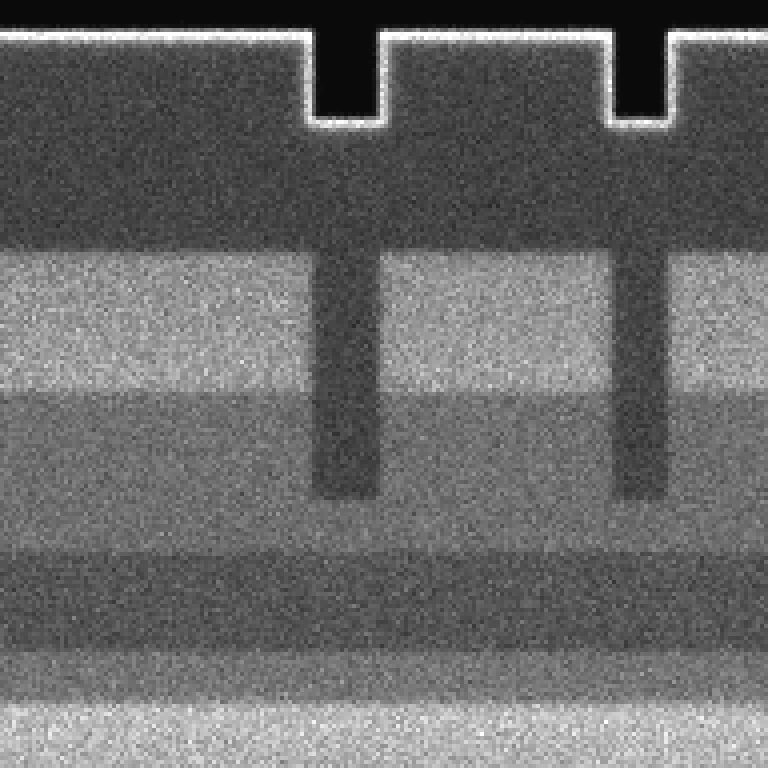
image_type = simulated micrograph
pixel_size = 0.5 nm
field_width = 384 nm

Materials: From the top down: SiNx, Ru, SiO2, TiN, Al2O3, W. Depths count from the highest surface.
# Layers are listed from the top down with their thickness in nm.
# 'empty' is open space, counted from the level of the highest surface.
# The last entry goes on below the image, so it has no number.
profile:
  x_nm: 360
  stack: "SiNx 110, Ru 70, SiO2 80, TiN 50, Al2O3 26, W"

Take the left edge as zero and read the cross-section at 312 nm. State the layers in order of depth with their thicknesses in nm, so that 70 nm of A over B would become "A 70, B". empty 44, SiNx 190, SiO2 26, TiN 50, Al2O3 26, W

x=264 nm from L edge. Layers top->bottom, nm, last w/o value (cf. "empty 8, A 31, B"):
SiNx 110, Ru 70, SiO2 80, TiN 50, Al2O3 26, W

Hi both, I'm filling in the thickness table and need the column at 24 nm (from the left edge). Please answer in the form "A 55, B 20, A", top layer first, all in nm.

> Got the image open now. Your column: SiNx 110, Ru 70, SiO2 80, TiN 50, Al2O3 26, W